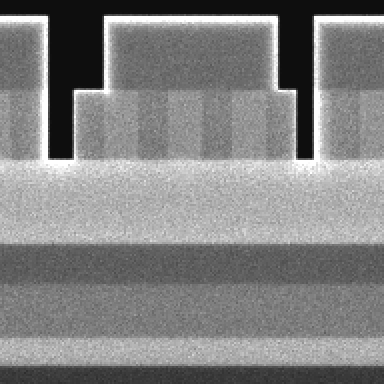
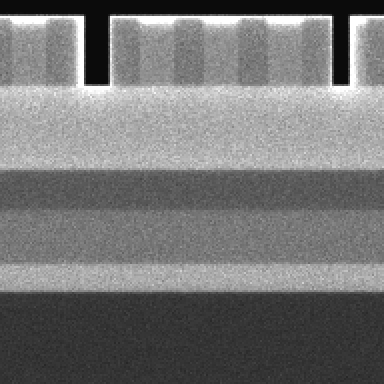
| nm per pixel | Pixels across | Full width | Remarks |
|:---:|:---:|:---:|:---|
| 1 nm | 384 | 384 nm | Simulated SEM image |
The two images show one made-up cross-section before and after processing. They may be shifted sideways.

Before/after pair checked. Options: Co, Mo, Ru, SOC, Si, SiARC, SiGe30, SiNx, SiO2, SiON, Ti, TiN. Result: removed SOC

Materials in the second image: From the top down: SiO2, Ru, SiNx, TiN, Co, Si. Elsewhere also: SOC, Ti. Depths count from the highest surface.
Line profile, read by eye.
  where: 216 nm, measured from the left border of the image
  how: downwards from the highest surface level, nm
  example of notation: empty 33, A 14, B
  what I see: SiO2 70, Ru 84, SiNx 40, TiN 54, Co 28, Si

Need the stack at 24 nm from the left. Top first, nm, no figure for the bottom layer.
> SiO2 70, Ru 84, SiNx 40, TiN 54, Co 28, Si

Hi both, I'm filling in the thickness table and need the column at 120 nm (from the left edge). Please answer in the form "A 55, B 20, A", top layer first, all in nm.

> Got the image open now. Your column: Ti 70, Ru 84, SiNx 40, TiN 54, Co 28, Si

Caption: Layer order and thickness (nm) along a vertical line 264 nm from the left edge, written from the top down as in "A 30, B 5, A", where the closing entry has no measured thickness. Ti 70, Ru 84, SiNx 40, TiN 54, Co 28, Si